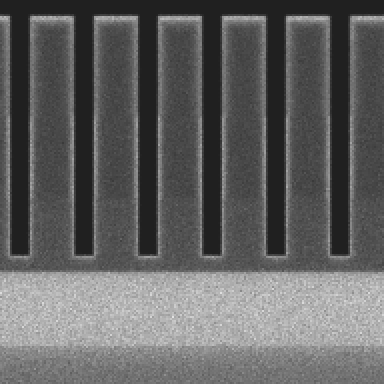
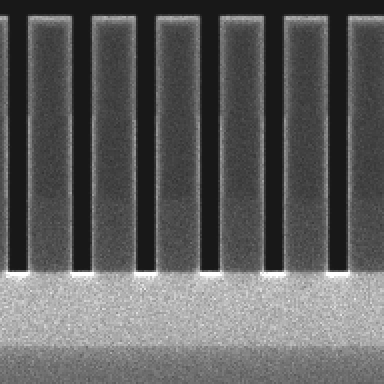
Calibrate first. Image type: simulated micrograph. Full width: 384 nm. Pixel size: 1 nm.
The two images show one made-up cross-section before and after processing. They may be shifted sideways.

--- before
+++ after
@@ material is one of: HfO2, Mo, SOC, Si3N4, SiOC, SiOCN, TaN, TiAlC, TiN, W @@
TiN removed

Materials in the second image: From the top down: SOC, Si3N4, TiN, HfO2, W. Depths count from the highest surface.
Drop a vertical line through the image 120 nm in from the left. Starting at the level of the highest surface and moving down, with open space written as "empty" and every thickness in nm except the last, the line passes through SOC 100, Si3N4 82, TiN 74, HfO2 74, W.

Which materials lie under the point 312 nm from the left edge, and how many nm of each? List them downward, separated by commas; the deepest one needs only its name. SOC 100, Si3N4 82, TiN 74, HfO2 74, W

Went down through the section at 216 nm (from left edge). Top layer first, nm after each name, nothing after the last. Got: empty 256, HfO2 74, W